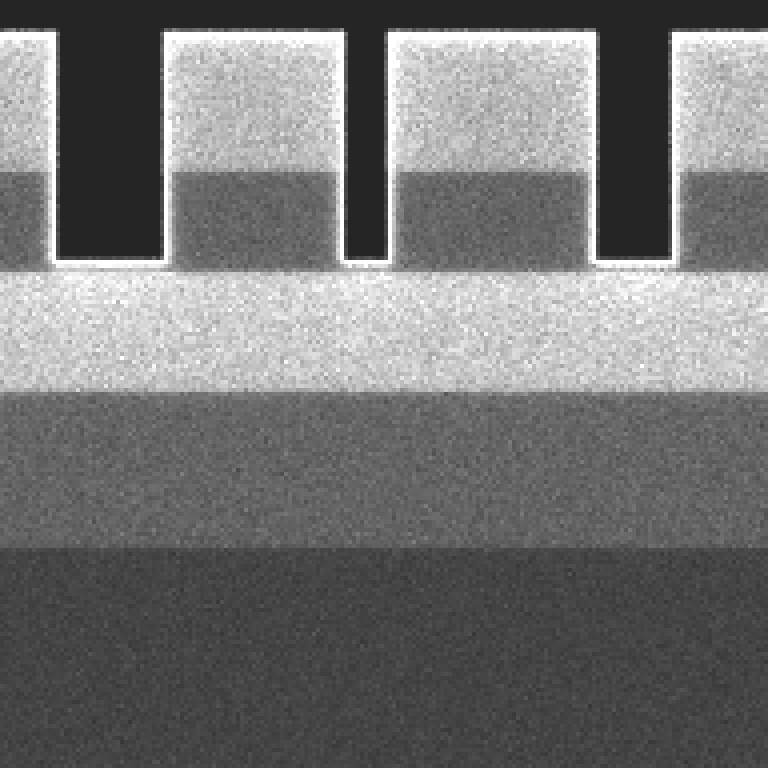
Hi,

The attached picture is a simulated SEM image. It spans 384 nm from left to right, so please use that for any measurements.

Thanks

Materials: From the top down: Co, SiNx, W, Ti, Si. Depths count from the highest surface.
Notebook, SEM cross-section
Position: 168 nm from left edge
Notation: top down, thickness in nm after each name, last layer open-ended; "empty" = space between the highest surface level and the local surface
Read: Co 70, SiNx 50, W 60, Ti 78, Si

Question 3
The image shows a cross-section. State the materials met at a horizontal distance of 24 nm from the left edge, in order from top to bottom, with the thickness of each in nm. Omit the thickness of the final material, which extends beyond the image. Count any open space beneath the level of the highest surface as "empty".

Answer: Co 70, SiNx 50, W 60, Ti 78, Si